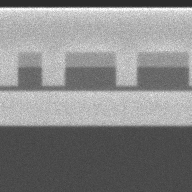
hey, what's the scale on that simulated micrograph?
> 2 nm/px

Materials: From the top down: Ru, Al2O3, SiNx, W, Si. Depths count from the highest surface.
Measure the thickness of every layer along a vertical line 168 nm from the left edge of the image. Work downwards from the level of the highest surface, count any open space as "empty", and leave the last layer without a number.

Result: Ru 88, Al2O3 30, SiNx 48, W 70, Si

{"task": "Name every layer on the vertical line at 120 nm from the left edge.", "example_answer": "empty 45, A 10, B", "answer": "Ru 156, SiNx 10, W 70, Si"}